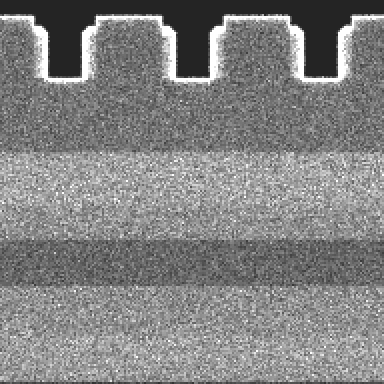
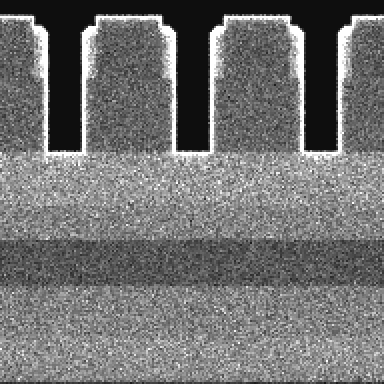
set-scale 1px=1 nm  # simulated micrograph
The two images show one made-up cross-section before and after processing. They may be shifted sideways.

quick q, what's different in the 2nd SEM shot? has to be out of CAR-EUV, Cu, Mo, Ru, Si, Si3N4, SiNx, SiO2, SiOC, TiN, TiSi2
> Si3N4 removed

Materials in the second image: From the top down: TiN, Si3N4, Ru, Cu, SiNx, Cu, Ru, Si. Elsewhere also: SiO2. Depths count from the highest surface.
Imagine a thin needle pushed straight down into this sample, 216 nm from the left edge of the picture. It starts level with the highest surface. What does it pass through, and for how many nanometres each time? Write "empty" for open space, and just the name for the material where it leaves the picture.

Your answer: empty 10, SiO2 52, Si3N4 74, Ru 54, Cu 34, SiNx 46, Cu 50, Ru 46, Si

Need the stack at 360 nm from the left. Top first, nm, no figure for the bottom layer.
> TiN 62, Si3N4 74, Ru 54, Cu 34, SiNx 46, Cu 50, Ru 46, Si